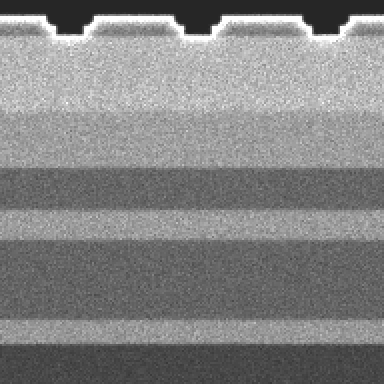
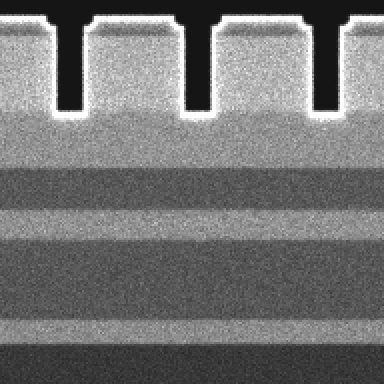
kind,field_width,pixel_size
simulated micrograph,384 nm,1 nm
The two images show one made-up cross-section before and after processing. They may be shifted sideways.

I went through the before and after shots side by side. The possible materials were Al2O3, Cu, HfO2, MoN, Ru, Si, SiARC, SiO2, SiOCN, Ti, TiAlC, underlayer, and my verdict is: removed, Ru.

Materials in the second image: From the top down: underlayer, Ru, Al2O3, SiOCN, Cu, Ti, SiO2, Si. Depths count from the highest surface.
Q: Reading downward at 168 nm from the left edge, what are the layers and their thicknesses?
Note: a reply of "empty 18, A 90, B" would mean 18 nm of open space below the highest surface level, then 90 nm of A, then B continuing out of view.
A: underlayer 20, Ru 76, Al2O3 56, SiOCN 42, Cu 30, Ti 80, SiO2 24, Si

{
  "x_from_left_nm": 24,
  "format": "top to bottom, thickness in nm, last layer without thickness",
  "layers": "underlayer 20, Ru 76, Al2O3 56, SiOCN 42, Cu 30, Ti 80, SiO2 24, Si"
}